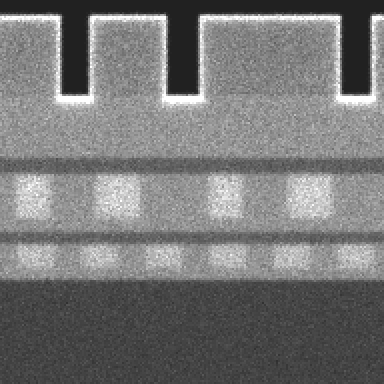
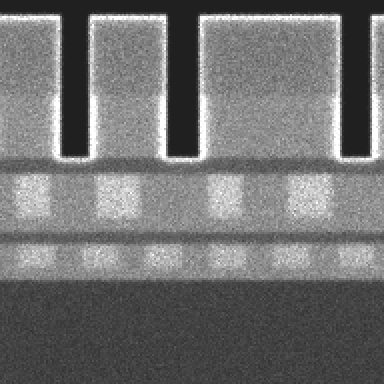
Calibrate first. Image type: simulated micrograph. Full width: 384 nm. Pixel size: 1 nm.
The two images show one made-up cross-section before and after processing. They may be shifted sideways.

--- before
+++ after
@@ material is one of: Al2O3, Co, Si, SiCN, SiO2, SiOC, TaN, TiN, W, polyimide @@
SiO2 removed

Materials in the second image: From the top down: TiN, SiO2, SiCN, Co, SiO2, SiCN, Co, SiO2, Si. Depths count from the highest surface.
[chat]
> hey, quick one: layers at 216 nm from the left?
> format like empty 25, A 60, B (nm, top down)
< TiN 80, SiO2 62, SiCN 16, Co 44, SiO2 14, SiCN 12, Co 24, SiO2 12, Si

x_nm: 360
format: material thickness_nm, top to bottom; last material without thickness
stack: empty 142, SiCN 16, SiO2 58, SiCN 12, Co 24, SiO2 12, Si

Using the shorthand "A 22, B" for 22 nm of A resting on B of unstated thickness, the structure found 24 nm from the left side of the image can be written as TiN 80, SiO2 62, SiCN 16, Co 44, SiO2 14, SiCN 12, Co 24, SiO2 12, Si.